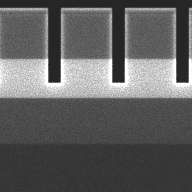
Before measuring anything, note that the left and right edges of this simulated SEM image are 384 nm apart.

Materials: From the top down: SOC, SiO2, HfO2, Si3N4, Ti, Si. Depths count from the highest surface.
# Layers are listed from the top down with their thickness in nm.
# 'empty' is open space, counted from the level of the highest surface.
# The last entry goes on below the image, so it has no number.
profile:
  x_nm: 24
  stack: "SOC 12, SiO2 90, HfO2 78, Si3N4 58, Ti 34, Si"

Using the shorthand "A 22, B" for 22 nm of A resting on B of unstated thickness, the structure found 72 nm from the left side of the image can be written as SOC 12, SiO2 90, HfO2 78, Si3N4 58, Ti 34, Si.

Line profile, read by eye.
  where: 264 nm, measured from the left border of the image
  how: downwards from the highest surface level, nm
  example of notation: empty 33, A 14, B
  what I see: SOC 12, SiO2 90, HfO2 78, Si3N4 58, Ti 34, Si